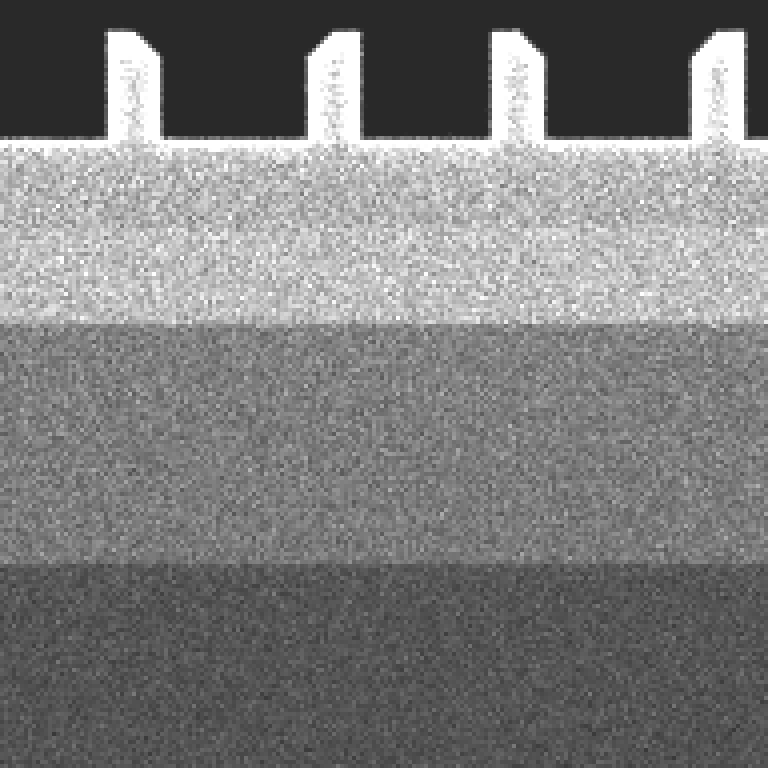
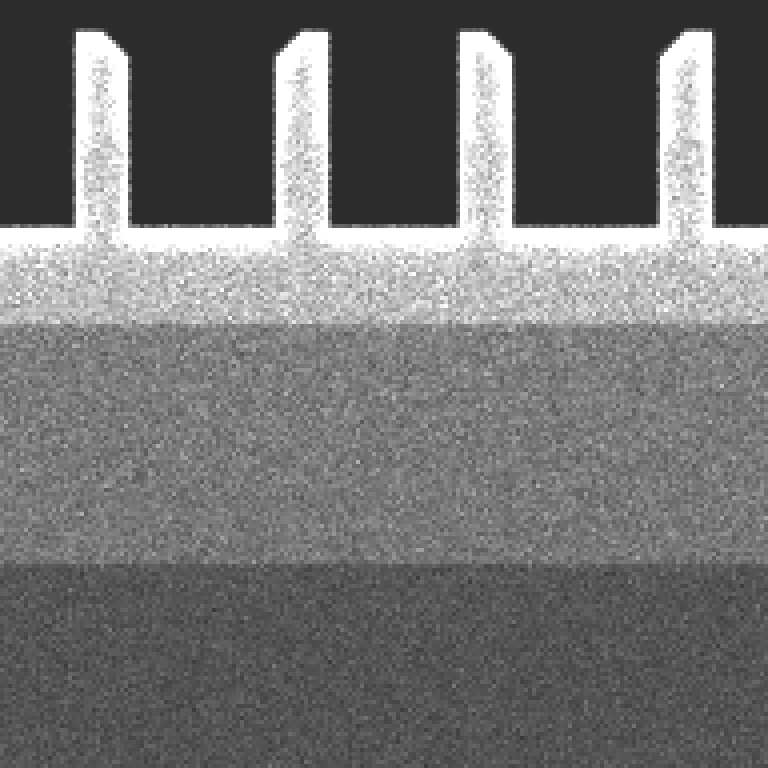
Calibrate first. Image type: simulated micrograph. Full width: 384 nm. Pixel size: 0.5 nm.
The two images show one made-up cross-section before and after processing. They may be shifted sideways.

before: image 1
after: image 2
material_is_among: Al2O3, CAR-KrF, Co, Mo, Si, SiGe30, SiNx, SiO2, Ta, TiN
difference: TiN, removed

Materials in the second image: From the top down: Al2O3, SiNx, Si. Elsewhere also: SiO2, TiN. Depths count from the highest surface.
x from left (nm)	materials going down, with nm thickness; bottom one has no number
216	empty 98, Al2O3 48, SiNx 120, Si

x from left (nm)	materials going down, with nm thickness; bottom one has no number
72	empty 98, Al2O3 48, SiNx 120, Si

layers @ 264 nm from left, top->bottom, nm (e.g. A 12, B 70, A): empty 98, Al2O3 48, SiNx 120, Si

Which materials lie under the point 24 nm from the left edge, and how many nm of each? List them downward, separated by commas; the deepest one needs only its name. empty 98, Al2O3 48, SiNx 120, Si